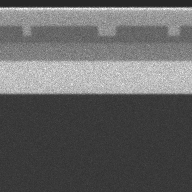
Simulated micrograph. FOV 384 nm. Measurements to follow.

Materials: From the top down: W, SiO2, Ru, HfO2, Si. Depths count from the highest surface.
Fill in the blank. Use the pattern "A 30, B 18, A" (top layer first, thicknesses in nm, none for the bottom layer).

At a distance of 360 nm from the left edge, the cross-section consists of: W 36, SiO2 34, Ru 36, HfO2 66, Si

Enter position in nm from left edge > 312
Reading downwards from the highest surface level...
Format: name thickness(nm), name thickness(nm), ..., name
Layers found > W 36, SiO2 34, Ru 36, HfO2 66, Si